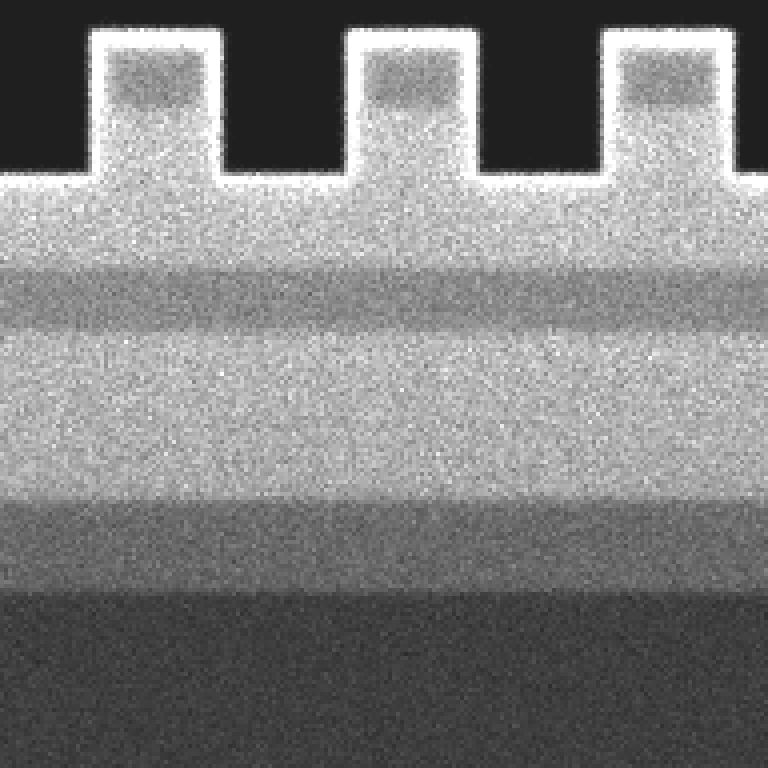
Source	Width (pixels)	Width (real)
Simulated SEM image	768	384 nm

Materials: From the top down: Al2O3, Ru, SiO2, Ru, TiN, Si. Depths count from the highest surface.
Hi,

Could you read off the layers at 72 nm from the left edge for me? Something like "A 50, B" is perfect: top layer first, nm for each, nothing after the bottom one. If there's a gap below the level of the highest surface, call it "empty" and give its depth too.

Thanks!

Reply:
Al2O3 38, Ru 80, SiO2 32, Ru 84, TiN 46, Si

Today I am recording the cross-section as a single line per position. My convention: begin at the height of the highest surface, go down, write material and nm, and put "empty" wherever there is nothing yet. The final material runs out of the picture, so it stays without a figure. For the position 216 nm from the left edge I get Al2O3 38, Ru 80, SiO2 32, Ru 84, TiN 46, Si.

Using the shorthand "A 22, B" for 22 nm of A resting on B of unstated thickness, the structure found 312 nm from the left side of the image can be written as Al2O3 38, Ru 80, SiO2 32, Ru 84, TiN 46, Si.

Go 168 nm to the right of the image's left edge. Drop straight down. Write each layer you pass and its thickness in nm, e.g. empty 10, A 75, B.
empty 72, Ru 46, SiO2 32, Ru 84, TiN 46, Si